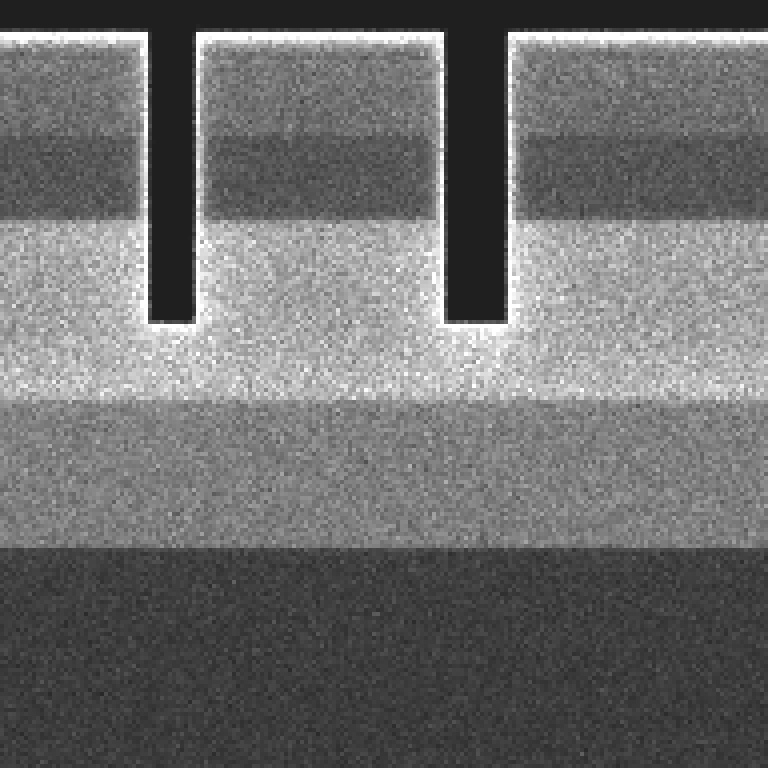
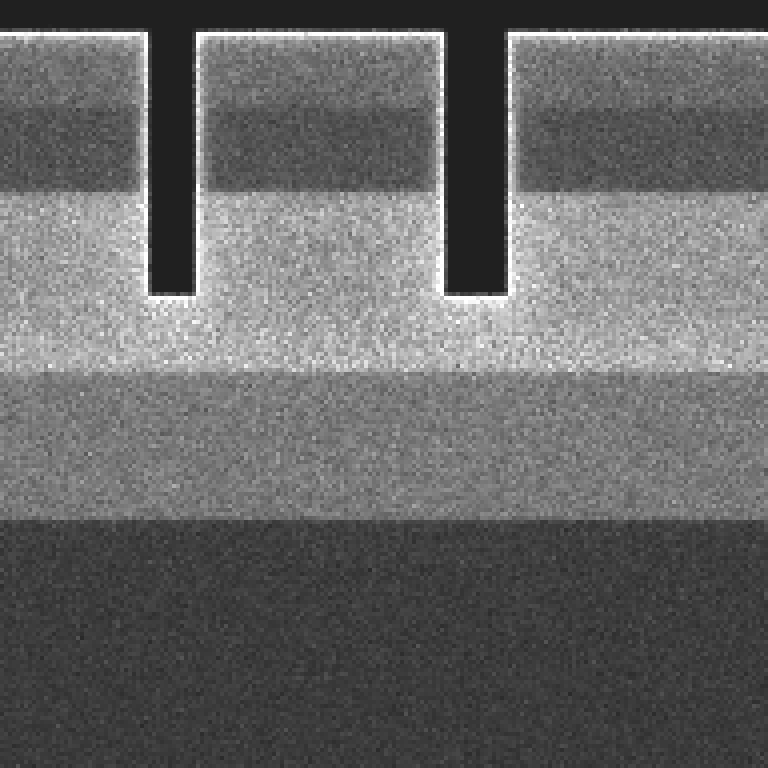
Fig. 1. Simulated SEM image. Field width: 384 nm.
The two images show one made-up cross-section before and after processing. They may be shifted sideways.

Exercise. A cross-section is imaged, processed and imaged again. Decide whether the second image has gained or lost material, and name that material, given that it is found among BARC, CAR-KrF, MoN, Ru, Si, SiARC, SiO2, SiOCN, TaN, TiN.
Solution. removed: SiARC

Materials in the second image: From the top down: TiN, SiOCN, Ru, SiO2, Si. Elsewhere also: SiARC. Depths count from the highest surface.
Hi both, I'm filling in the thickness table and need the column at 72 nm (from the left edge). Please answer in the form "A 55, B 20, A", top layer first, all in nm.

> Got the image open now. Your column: TiN 38, SiOCN 42, Ru 90, SiO2 74, Si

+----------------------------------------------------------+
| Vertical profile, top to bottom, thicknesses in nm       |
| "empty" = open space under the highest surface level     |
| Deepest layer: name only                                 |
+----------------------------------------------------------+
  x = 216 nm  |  TiN 38, SiOCN 42, Ru 90, SiO2 74, Si